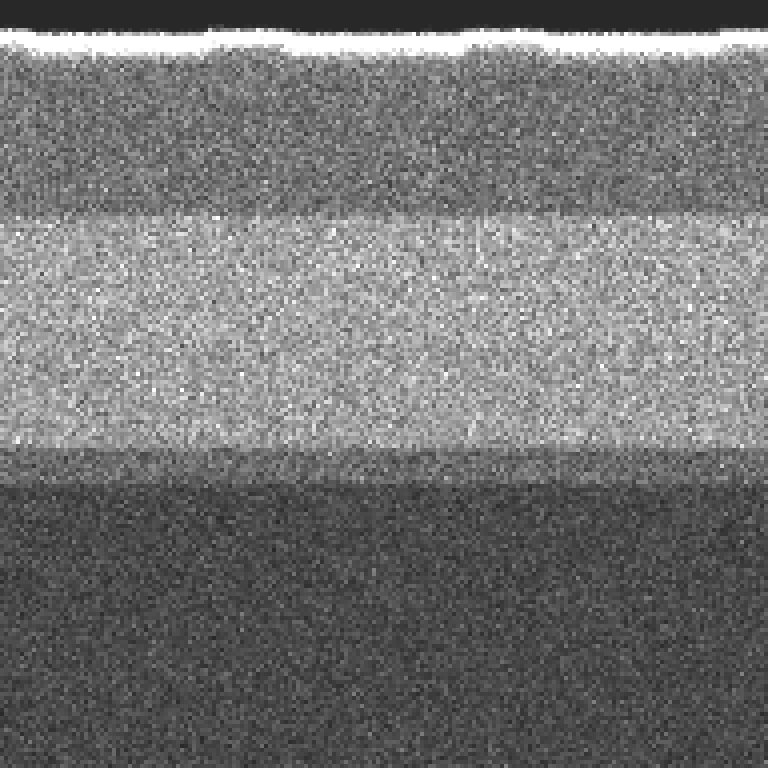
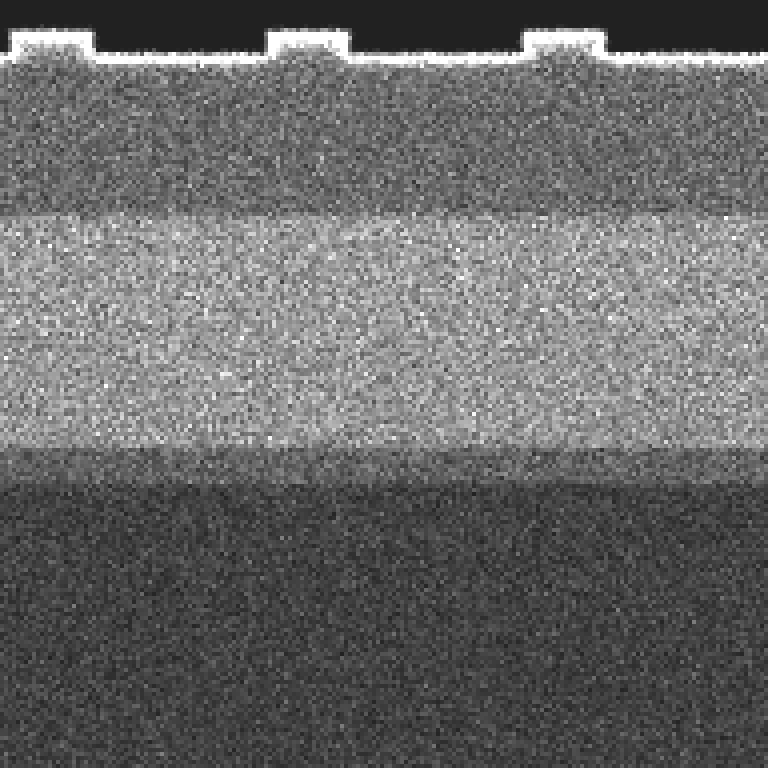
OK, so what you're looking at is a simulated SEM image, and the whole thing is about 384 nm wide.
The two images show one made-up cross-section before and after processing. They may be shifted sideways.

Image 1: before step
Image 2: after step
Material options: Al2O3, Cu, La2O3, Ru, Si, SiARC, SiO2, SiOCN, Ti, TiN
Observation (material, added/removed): SiO2, removed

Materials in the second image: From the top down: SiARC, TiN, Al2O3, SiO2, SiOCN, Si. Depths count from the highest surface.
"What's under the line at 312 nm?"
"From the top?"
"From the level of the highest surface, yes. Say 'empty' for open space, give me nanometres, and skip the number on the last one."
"empty 12, TiN 80, Al2O3 64, SiO2 52, SiOCN 18, Si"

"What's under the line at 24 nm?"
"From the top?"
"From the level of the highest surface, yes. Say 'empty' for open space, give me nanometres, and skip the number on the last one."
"SiARC 12, TiN 80, Al2O3 64, SiO2 52, SiOCN 18, Si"